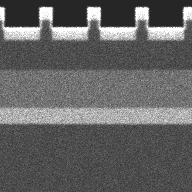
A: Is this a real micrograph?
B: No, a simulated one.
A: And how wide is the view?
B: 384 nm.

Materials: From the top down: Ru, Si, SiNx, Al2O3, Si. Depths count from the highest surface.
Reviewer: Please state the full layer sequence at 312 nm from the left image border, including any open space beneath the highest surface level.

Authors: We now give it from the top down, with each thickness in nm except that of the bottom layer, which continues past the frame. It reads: empty 40, Ru 24, Si 60, SiNx 76, Al2O3 32, Si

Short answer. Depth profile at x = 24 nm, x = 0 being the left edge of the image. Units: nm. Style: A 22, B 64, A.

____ empty 40, Ru 24, Si 60, SiNx 76, Al2O3 32, Si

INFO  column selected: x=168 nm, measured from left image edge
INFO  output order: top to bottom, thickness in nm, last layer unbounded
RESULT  empty 40, Ru 24, Si 60, SiNx 76, Al2O3 32, Si